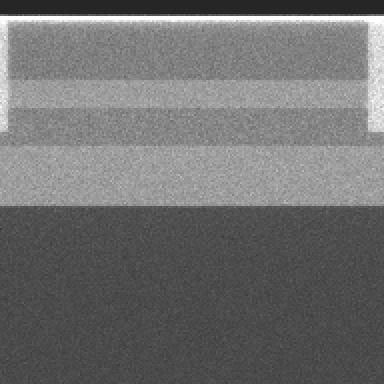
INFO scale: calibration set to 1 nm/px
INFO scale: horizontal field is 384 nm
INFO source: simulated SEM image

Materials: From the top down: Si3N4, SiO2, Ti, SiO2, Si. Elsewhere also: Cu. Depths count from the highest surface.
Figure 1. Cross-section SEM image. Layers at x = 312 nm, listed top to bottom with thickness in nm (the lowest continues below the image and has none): Si3N4 64, SiO2 28, Ti 38, SiO2 60, Si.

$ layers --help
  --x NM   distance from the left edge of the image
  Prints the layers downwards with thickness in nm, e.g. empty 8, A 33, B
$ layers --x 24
Si3N4 64, SiO2 28, Ti 38, SiO2 60, Si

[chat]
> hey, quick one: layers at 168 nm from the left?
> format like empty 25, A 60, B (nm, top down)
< Si3N4 64, SiO2 28, Ti 38, SiO2 60, Si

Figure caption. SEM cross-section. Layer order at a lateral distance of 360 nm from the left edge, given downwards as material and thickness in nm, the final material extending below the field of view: Si3N4 64, SiO2 28, Ti 38, SiO2 60, Si